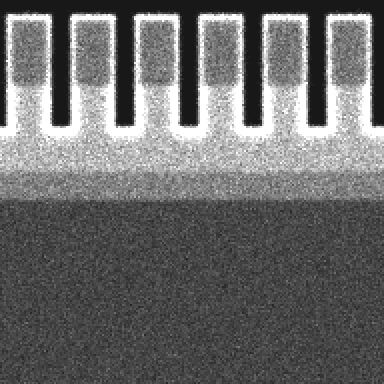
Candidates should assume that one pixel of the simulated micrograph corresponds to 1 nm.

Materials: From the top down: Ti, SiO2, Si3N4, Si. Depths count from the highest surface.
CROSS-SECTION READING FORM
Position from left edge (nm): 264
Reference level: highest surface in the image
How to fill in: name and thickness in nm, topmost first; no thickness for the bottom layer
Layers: Ti 70, SiO2 86, Si3N4 28, Si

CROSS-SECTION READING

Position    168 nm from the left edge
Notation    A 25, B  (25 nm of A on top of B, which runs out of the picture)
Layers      Ti 70, SiO2 86, Si3N4 28, Si